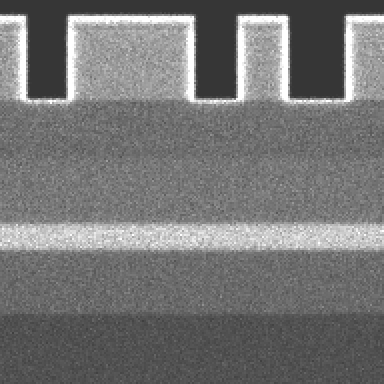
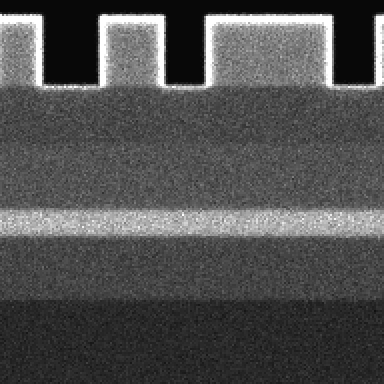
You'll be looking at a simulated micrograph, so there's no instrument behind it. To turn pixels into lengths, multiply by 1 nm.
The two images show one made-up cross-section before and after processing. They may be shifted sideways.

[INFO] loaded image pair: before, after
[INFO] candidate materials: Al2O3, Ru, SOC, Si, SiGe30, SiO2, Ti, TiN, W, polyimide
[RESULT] removed SOC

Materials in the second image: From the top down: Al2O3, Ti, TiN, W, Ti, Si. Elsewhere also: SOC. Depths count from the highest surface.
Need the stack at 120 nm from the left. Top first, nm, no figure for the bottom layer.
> Al2O3 70, Ti 58, TiN 66, W 26, Ti 64, Si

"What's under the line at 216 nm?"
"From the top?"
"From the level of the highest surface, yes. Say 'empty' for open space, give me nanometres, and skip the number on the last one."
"Al2O3 70, Ti 58, TiN 66, W 26, Ti 64, Si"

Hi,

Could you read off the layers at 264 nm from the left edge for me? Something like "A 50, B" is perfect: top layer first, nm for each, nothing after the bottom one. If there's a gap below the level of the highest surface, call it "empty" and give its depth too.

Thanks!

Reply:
Al2O3 70, Ti 58, TiN 66, W 26, Ti 64, Si